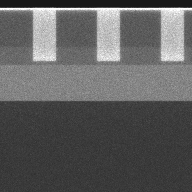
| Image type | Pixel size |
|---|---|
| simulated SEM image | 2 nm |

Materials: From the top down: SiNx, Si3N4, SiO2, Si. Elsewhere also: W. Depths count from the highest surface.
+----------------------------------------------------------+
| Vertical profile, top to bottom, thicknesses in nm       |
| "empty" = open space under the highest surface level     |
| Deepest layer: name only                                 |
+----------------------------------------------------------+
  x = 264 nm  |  SiNx 78, Si3N4 36, SiO2 72, Si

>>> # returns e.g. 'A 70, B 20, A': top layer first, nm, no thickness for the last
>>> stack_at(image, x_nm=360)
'W 106, Si3N4 8, SiO2 72, Si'